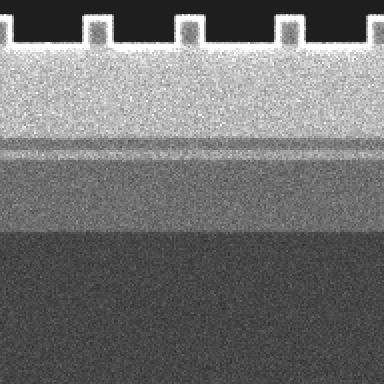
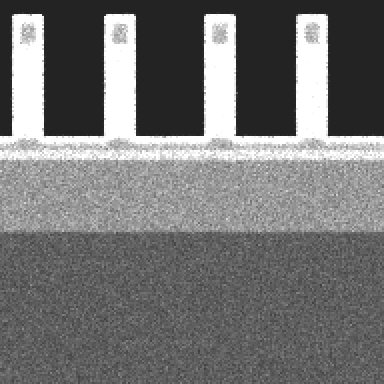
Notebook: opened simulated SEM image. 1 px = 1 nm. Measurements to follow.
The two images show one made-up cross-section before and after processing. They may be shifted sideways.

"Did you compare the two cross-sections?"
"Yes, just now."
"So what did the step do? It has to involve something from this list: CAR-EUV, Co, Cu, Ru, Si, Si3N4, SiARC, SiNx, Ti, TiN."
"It removed Ru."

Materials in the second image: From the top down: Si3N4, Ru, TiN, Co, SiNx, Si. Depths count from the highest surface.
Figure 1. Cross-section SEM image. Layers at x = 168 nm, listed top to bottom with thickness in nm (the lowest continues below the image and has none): empty 122, TiN 12, Co 10, SiNx 72, Si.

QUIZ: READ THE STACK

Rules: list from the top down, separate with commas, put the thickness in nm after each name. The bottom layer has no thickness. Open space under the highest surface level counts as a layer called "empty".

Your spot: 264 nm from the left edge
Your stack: empty 122, TiN 12, Co 10, SiNx 72, Si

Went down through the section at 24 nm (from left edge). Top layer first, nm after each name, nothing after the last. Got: Si3N4 28, Ru 94, TiN 12, Co 10, SiNx 72, Si